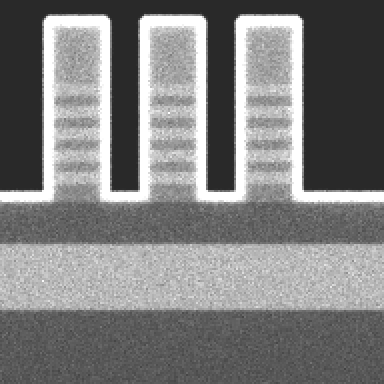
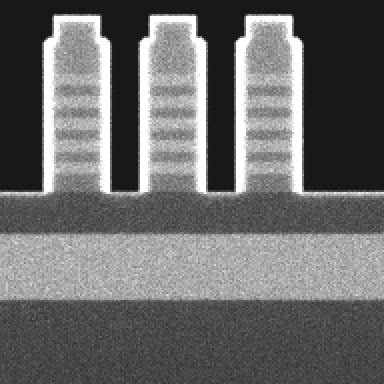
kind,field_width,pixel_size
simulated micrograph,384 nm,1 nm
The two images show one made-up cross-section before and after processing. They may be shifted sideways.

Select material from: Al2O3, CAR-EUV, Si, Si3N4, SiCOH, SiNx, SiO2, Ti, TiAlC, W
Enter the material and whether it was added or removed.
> Al2O3 / removed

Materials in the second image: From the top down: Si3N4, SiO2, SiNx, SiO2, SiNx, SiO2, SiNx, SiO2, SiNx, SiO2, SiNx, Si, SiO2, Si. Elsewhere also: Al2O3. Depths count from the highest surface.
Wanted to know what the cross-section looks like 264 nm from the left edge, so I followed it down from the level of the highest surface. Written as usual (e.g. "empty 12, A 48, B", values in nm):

Si3N4 58, SiO2 12, SiNx 10, SiO2 12, SiNx 10, SiO2 12, SiNx 10, SiO2 12, SiNx 10, SiO2 12, SiNx 18, Si 42, SiO2 66, Si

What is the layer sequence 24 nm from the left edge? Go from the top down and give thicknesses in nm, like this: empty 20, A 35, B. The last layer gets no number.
empty 176, Si 42, SiO2 66, Si